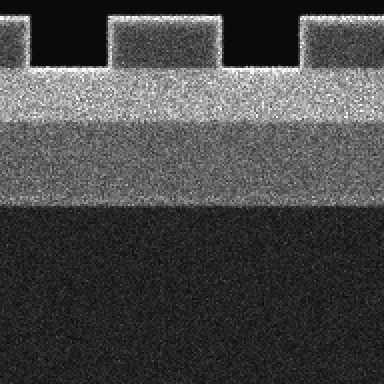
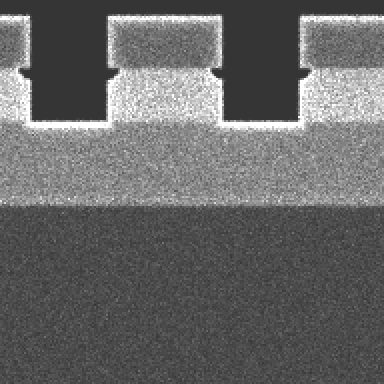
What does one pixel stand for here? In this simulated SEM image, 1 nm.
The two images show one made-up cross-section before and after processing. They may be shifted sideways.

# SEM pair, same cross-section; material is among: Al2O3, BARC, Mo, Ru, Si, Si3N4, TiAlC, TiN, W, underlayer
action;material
removed;W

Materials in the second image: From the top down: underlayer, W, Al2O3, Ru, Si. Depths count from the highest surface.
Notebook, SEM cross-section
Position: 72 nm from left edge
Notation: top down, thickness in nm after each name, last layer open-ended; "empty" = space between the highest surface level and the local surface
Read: empty 106, Al2O3 74, Ru 10, Si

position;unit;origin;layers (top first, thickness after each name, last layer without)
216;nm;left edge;underlayer 52, empty 12, W 42, Al2O3 74, Ru 10, Si